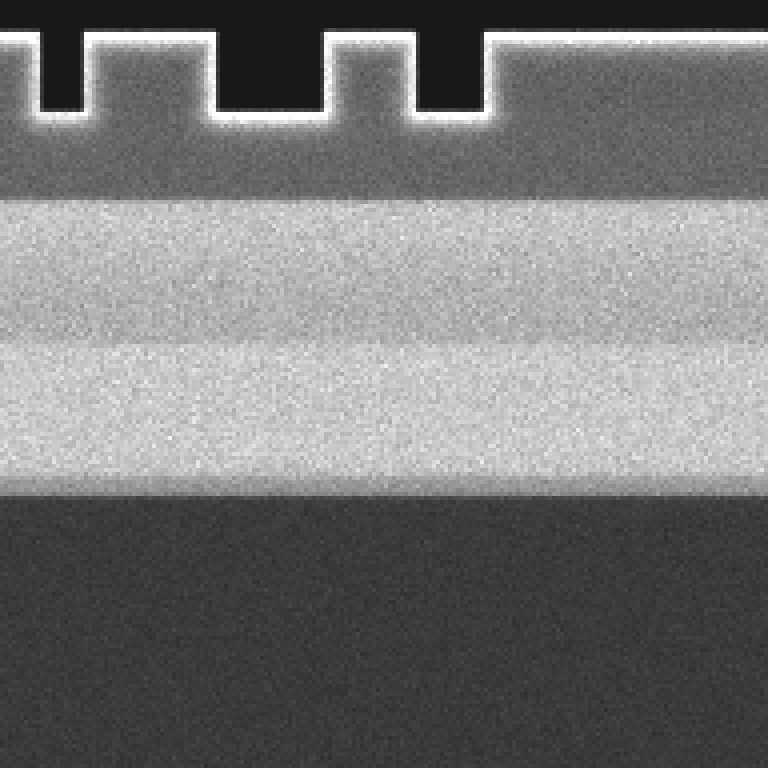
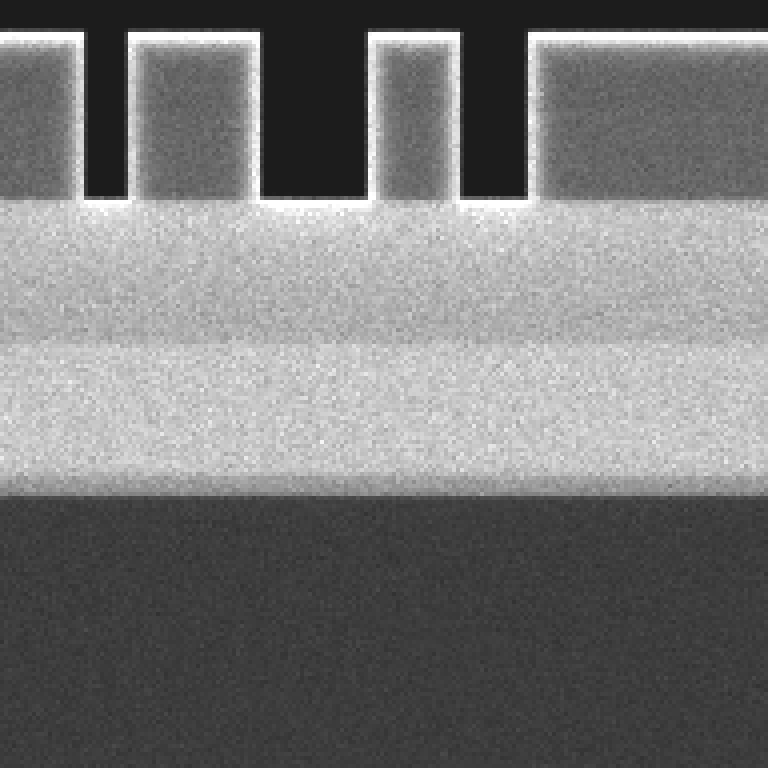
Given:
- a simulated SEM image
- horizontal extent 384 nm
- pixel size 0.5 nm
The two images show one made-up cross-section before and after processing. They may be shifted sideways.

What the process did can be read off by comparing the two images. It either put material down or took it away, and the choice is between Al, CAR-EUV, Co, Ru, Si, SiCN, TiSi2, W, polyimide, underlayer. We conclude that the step removed underlayer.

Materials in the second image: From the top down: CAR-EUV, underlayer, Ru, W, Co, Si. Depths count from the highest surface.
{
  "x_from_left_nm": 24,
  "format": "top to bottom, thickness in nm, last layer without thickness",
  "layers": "CAR-EUV 40, underlayer 44, Ru 72, W 66, Co 10, Si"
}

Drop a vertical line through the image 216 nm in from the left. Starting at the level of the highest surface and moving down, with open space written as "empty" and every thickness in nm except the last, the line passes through CAR-EUV 40, underlayer 44, Ru 72, W 66, Co 10, Si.